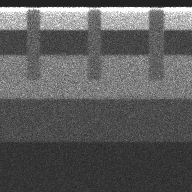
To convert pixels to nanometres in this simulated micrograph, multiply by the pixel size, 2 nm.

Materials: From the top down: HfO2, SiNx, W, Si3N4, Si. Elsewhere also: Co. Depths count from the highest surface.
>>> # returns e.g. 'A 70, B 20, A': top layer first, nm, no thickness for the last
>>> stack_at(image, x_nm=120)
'HfO2 44, SiNx 50, W 88, Si3N4 86, Si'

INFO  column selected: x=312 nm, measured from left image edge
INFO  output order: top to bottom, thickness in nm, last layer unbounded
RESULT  Co 144, W 38, Si3N4 86, Si